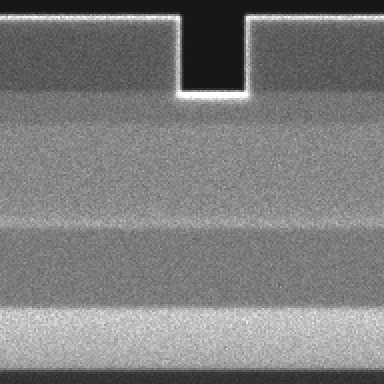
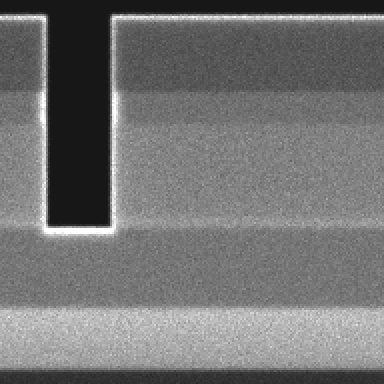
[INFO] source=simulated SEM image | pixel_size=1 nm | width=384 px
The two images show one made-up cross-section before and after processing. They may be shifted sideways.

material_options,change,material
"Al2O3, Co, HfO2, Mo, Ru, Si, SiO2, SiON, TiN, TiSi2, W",removed,Co and Ru and SiO2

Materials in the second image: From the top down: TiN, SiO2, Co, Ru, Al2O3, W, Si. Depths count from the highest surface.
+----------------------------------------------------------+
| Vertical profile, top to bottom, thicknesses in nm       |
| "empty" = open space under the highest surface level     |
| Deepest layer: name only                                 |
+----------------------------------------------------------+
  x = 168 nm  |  TiN 76, SiO2 32, Co 94, Ru 10, Al2O3 80, W 62, Si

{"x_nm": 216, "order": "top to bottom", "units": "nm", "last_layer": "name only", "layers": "TiN 76, SiO2 32, Co 94, Ru 10, Al2O3 80, W 62, Si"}